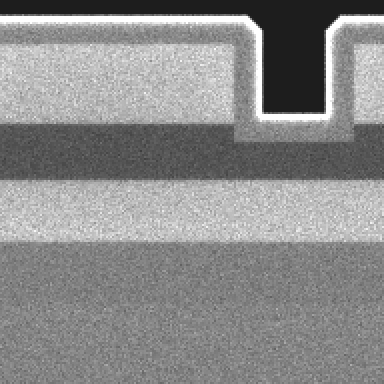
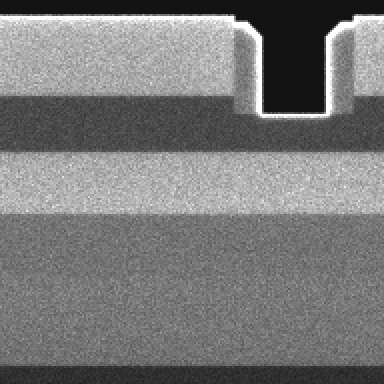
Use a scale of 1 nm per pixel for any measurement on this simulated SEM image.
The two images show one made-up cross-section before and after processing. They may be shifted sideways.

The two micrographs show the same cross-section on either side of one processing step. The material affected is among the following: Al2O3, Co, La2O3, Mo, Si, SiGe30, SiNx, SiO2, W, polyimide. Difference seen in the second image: Al2O3 removed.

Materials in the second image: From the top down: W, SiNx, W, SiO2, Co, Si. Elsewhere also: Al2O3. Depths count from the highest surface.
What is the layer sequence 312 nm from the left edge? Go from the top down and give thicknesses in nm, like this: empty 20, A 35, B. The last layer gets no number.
empty 98, SiNx 38, W 62, SiO2 62, Co 90, Si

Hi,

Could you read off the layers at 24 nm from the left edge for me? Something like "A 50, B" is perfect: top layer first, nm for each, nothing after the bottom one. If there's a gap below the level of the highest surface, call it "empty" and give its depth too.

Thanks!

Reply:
W 80, SiNx 56, W 62, SiO2 62, Co 90, Si